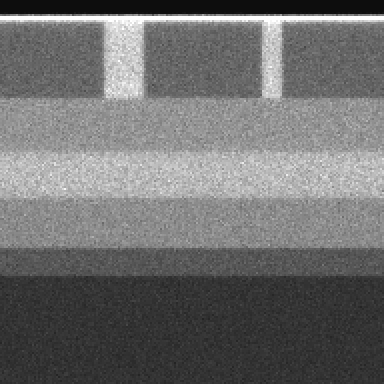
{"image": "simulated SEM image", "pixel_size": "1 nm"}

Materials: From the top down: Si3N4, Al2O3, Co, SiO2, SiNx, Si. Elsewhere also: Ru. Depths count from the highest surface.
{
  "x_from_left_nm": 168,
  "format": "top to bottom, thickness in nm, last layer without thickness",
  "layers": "Si3N4 82, Al2O3 54, Co 46, SiO2 50, SiNx 28, Si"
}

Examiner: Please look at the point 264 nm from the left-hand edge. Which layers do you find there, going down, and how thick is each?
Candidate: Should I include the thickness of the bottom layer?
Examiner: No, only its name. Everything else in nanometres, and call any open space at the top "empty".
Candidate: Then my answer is Ru 82, Al2O3 54, Co 46, SiO2 50, SiNx 28, Si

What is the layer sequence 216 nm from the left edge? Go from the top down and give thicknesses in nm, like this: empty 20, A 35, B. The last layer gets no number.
Si3N4 82, Al2O3 54, Co 46, SiO2 50, SiNx 28, Si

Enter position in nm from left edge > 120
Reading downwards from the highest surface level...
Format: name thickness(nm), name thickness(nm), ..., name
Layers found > Ru 82, Al2O3 54, Co 46, SiO2 50, SiNx 28, Si